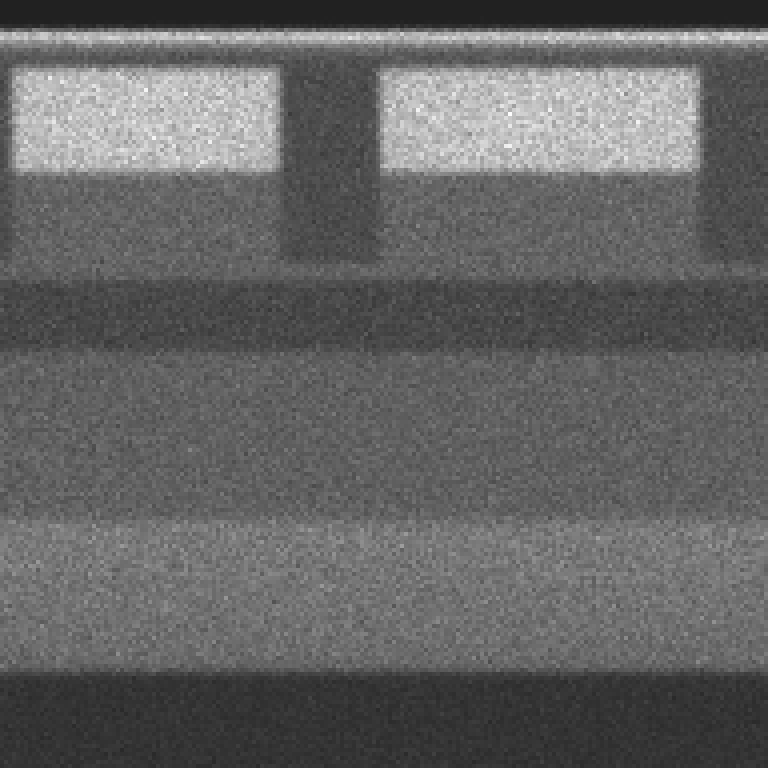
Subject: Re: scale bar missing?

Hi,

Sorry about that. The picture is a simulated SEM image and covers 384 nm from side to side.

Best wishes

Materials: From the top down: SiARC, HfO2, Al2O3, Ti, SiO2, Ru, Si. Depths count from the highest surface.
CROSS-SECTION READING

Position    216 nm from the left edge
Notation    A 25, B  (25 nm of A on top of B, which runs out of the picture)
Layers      SiARC 18, HfO2 52, Al2O3 54, Ti 36, SiO2 84, Ru 76, Si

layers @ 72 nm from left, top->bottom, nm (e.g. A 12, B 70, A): SiARC 18, HfO2 52, Al2O3 54, Ti 36, SiO2 84, Ru 76, Si